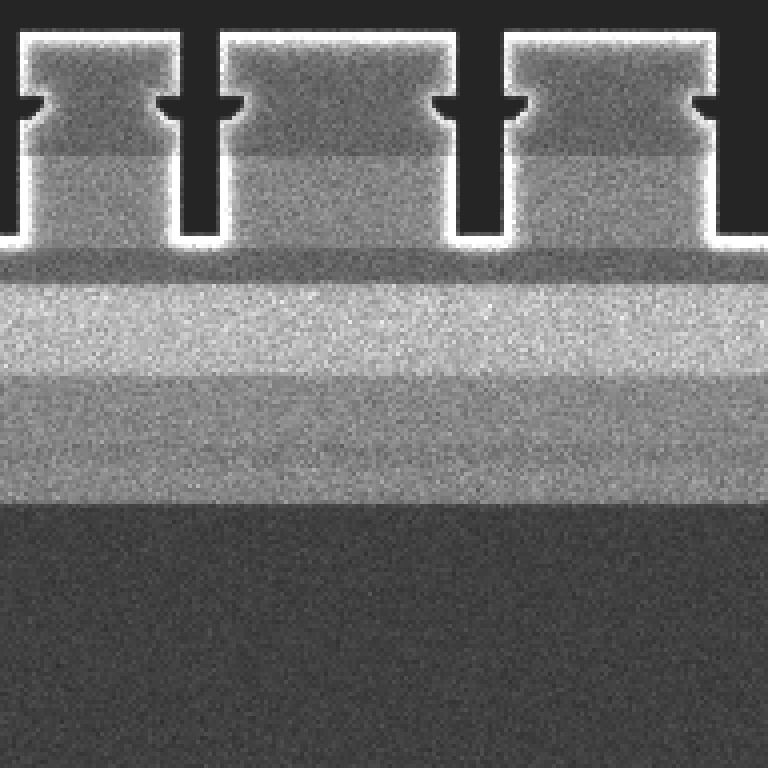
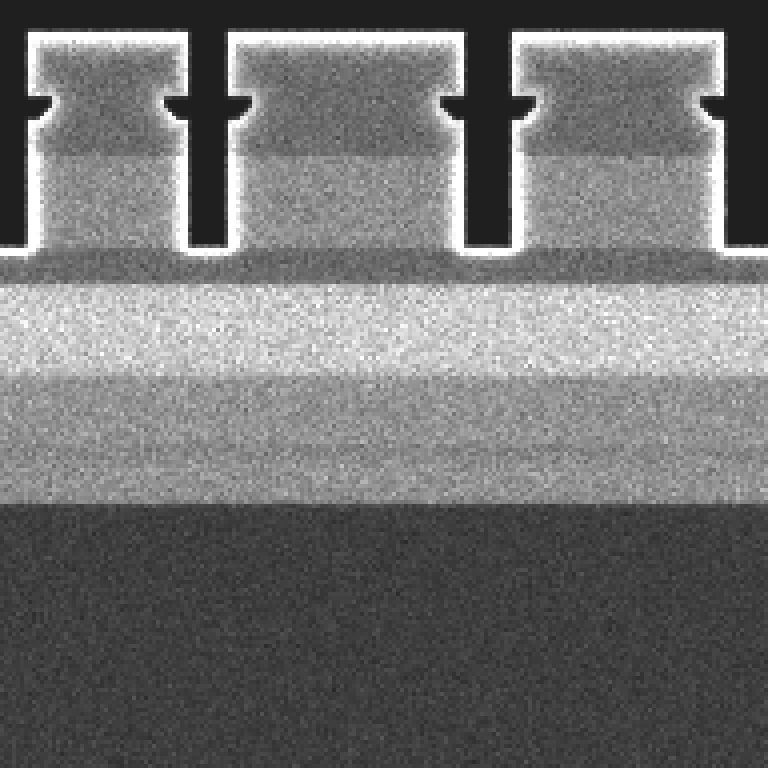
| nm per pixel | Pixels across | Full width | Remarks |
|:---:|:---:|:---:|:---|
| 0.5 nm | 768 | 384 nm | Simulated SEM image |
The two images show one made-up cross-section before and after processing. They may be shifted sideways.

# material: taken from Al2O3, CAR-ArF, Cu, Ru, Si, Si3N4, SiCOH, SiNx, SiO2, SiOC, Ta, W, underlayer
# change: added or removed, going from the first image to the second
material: SiO2
change: removed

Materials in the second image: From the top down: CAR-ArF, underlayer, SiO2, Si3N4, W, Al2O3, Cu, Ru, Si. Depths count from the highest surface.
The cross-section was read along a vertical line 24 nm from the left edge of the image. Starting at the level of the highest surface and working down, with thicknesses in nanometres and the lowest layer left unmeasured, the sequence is CAR-ArF 32, empty 6, underlayer 24, SiO2 46, Si3N4 18, W 46, Al2O3 34, Cu 10, Ru 20, Si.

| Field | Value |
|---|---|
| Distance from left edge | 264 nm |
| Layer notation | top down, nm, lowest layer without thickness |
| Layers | CAR-ArF 32, empty 8, underlayer 22, SiO2 46, Si3N4 18, W 46, Al2O3 34, Cu 10, Ru 20, Si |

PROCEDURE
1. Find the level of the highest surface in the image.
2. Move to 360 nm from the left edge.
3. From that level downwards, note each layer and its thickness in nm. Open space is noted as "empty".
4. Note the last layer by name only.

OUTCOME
CAR-ArF 32, empty 12, underlayer 18, SiO2 46, Si3N4 18, W 46, Al2O3 34, Cu 10, Ru 20, Si